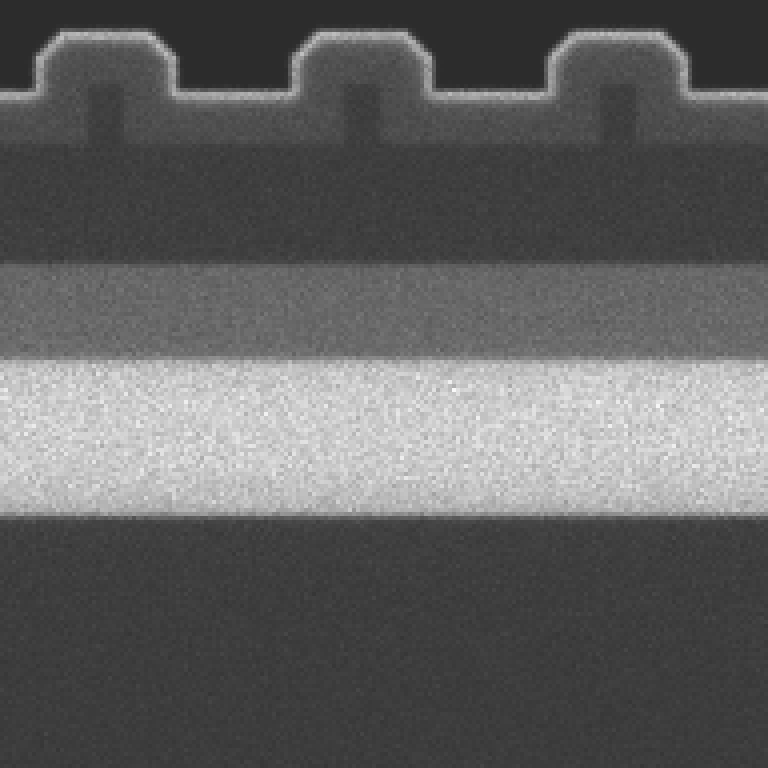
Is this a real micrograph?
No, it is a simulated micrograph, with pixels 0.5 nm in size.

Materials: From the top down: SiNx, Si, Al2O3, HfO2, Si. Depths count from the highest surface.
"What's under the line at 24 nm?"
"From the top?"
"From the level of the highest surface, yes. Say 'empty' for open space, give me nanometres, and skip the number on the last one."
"empty 6, SiNx 50, Si 60, Al2O3 48, HfO2 78, Si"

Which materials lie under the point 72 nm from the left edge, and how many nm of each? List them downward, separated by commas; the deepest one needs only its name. SiNx 56, Si 60, Al2O3 48, HfO2 78, Si